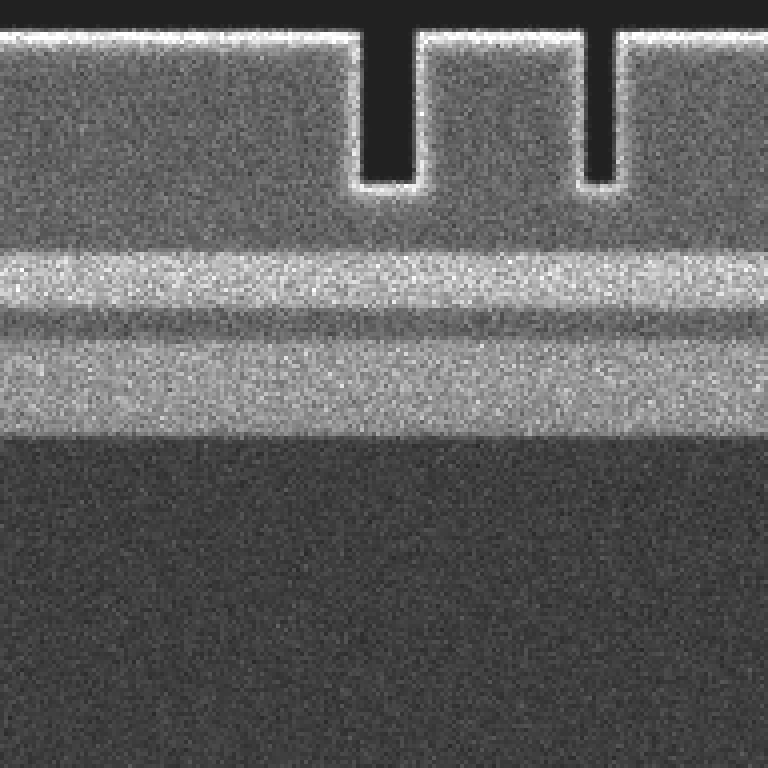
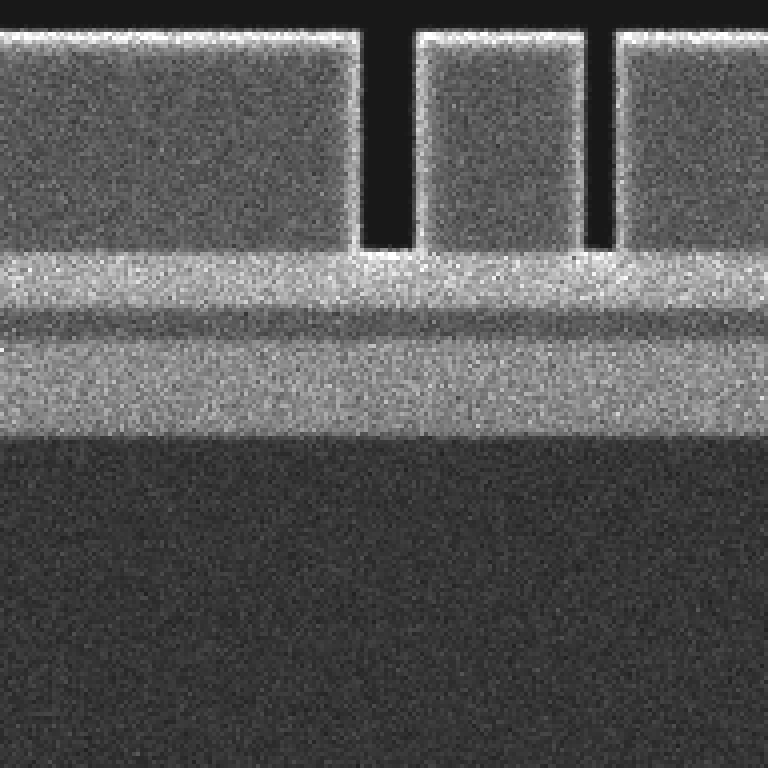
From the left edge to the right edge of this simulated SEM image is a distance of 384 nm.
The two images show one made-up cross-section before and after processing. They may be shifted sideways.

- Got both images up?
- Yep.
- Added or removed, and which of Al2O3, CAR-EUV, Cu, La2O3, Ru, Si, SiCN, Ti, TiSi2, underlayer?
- removed, underlayer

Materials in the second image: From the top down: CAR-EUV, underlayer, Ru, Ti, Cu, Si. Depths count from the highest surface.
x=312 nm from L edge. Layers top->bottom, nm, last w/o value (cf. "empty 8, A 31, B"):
CAR-EUV 76, underlayer 34, Ru 28, Ti 16, Cu 48, Si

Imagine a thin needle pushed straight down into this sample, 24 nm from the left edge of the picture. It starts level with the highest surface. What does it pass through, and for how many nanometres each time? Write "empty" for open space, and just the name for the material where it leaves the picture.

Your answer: CAR-EUV 76, underlayer 34, Ru 28, Ti 16, Cu 48, Si